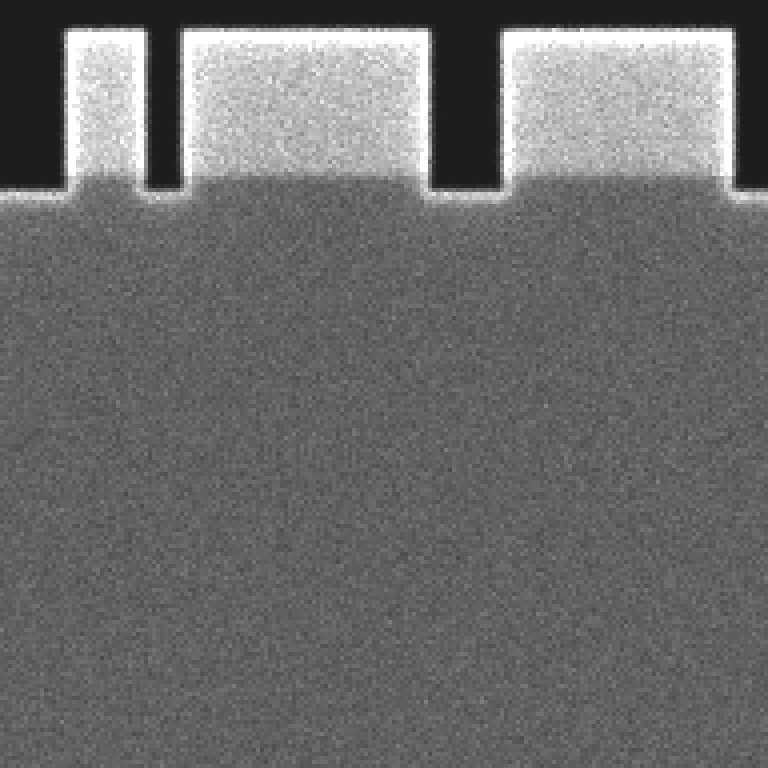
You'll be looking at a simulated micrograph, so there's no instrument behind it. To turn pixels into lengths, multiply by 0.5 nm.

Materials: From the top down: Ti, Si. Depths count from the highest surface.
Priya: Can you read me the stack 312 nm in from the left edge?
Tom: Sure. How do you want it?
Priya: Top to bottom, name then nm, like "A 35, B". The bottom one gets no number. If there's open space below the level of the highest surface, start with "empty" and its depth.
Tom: Ti 72, Si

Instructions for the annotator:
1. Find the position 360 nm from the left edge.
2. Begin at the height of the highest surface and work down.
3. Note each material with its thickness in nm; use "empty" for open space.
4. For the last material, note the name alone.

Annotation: Ti 72, Si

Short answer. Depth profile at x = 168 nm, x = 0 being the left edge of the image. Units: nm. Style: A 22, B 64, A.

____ Ti 72, Si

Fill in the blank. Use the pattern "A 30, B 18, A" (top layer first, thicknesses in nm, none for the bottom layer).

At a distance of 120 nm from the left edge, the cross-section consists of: Ti 72, Si